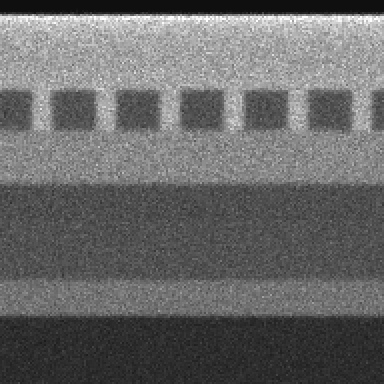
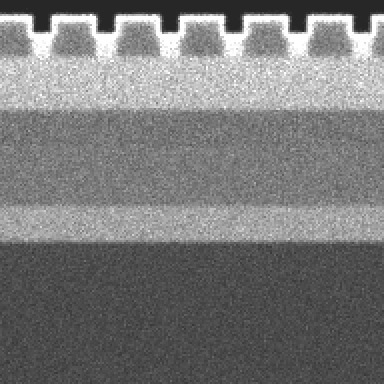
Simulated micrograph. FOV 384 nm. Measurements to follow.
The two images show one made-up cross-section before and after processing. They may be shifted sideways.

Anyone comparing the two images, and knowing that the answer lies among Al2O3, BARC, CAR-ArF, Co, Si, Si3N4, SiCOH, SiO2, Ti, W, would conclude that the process removed W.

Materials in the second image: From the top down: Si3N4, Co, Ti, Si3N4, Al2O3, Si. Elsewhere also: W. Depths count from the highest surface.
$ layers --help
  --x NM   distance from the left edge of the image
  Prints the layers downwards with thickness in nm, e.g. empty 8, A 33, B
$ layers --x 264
Si3N4 40, Co 54, Ti 36, Si3N4 60, Al2O3 36, Si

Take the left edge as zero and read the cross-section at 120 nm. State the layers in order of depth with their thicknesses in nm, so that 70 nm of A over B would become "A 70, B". Si3N4 40, Co 54, Ti 36, Si3N4 60, Al2O3 36, Si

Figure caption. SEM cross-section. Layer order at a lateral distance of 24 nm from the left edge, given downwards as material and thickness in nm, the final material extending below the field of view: Si3N4 40, Co 54, Ti 36, Si3N4 60, Al2O3 36, Si